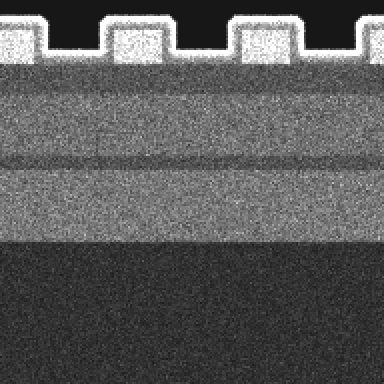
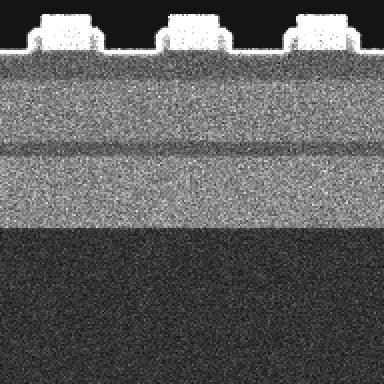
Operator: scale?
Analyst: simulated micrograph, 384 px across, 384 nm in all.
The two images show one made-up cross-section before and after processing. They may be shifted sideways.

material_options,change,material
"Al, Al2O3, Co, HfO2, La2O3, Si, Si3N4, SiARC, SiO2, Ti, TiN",removed,SiO2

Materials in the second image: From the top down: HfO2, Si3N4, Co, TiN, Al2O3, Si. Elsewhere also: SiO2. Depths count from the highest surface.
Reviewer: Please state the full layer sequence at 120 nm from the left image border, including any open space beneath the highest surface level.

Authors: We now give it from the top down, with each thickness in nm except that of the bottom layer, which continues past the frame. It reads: empty 34, Si3N4 30, Co 62, TiN 14, Al2O3 72, Si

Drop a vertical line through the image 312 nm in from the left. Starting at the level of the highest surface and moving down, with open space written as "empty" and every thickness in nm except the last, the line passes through HfO2 34, Si3N4 30, Co 62, TiN 14, Al2O3 72, Si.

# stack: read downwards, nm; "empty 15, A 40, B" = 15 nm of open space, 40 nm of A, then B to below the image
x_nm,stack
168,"empty 12, SiO2 22, Si3N4 30, Co 62, TiN 14, Al2O3 72, Si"